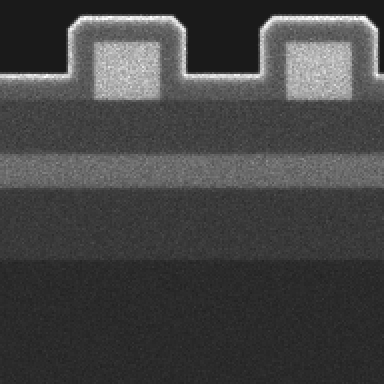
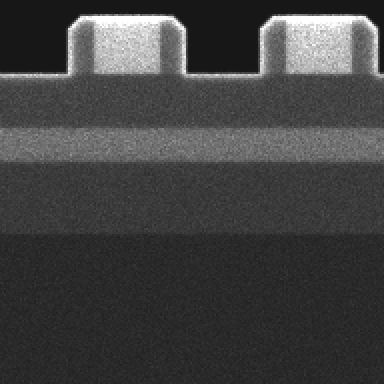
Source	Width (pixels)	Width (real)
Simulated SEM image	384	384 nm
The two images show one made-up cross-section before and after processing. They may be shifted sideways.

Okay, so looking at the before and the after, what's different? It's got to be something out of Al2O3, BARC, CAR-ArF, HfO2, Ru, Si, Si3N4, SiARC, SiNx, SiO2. Al2O3, removed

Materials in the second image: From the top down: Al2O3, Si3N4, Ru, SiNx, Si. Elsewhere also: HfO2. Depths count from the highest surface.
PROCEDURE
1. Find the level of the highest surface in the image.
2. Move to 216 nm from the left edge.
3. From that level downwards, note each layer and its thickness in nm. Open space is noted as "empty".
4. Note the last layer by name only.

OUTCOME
empty 58, Si3N4 54, Ru 34, SiNx 72, Si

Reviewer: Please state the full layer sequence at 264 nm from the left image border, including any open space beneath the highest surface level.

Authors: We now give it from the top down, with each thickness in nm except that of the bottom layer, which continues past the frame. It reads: empty 8, Al2O3 50, Si3N4 54, Ru 34, SiNx 72, Si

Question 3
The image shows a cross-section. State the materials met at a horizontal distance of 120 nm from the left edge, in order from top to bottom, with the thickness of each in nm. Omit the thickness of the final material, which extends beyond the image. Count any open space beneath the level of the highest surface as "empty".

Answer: HfO2 58, Si3N4 54, Ru 34, SiNx 72, Si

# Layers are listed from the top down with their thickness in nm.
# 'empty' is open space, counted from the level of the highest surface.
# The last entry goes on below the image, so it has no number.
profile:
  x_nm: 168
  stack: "Al2O3 58, Si3N4 54, Ru 34, SiNx 72, Si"